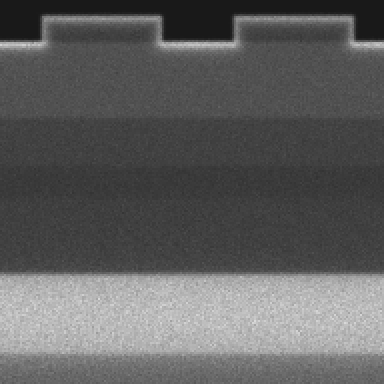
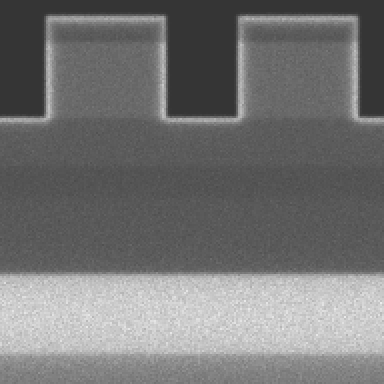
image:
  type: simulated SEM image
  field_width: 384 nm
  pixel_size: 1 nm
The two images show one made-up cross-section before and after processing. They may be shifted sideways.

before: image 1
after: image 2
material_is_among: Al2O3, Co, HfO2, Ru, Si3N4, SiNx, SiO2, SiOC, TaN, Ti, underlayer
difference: SiO2, removed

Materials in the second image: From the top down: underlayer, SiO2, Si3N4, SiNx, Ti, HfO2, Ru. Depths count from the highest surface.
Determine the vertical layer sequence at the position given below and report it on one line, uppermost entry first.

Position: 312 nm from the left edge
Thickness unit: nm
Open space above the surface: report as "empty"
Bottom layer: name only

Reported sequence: underlayer 26, SiO2 76, Si3N4 48, SiNx 32, Ti 76, HfO2 80, Ru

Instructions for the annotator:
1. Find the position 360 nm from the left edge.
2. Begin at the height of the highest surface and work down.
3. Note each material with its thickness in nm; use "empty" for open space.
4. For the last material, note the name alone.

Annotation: empty 102, Si3N4 48, SiNx 32, Ti 76, HfO2 80, Ru